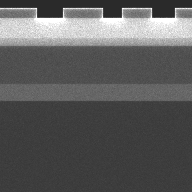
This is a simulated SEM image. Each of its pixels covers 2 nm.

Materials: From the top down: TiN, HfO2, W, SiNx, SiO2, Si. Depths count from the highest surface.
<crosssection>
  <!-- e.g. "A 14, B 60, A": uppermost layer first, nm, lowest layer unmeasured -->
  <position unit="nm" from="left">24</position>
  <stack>TiN 20, HfO2 40, W 16, SiNx 76, SiO2 34, Si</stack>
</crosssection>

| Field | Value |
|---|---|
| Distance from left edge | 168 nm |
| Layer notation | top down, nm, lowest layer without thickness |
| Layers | TiN 20, HfO2 40, W 16, SiNx 76, SiO2 34, Si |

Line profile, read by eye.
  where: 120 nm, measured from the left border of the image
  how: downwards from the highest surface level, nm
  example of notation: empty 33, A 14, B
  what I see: empty 20, HfO2 40, W 16, SiNx 76, SiO2 34, Si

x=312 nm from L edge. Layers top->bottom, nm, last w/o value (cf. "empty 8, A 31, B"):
empty 20, HfO2 40, W 16, SiNx 76, SiO2 34, Si